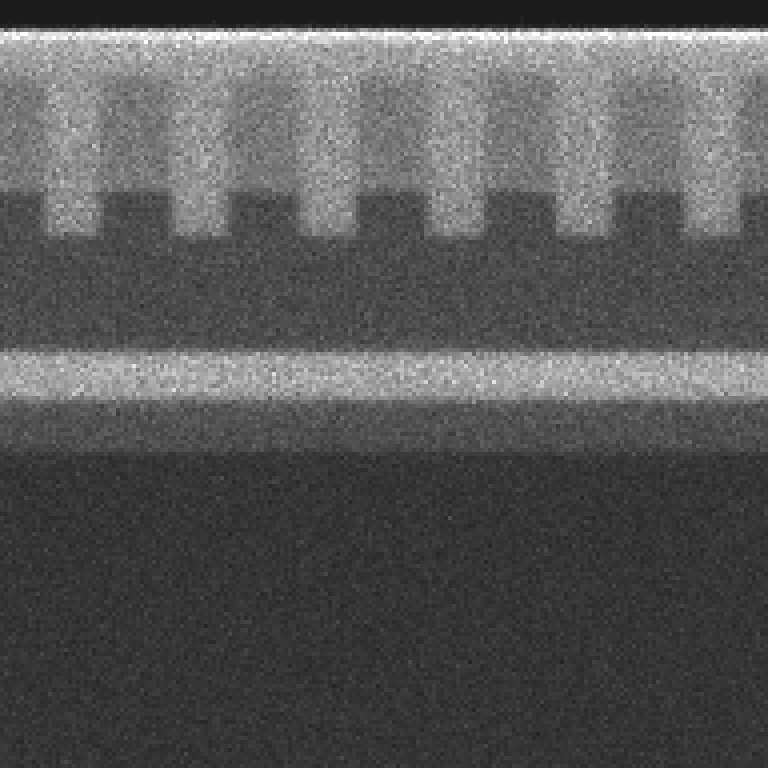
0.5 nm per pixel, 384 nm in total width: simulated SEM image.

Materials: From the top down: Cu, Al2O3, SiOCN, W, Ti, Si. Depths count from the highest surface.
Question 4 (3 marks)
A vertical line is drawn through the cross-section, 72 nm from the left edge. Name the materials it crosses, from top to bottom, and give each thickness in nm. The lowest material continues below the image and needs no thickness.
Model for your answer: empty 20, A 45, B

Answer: Cu 22, Al2O3 58, SiOCN 80, W 24, Ti 26, Si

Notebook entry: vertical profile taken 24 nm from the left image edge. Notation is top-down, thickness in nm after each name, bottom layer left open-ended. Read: Cu 102, SiOCN 58, W 24, Ti 26, Si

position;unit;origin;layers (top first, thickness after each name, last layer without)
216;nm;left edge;Cu 102, SiOCN 58, W 24, Ti 26, Si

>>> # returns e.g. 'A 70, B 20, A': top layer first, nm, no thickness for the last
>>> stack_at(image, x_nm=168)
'Cu 102, SiOCN 58, W 24, Ti 26, Si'